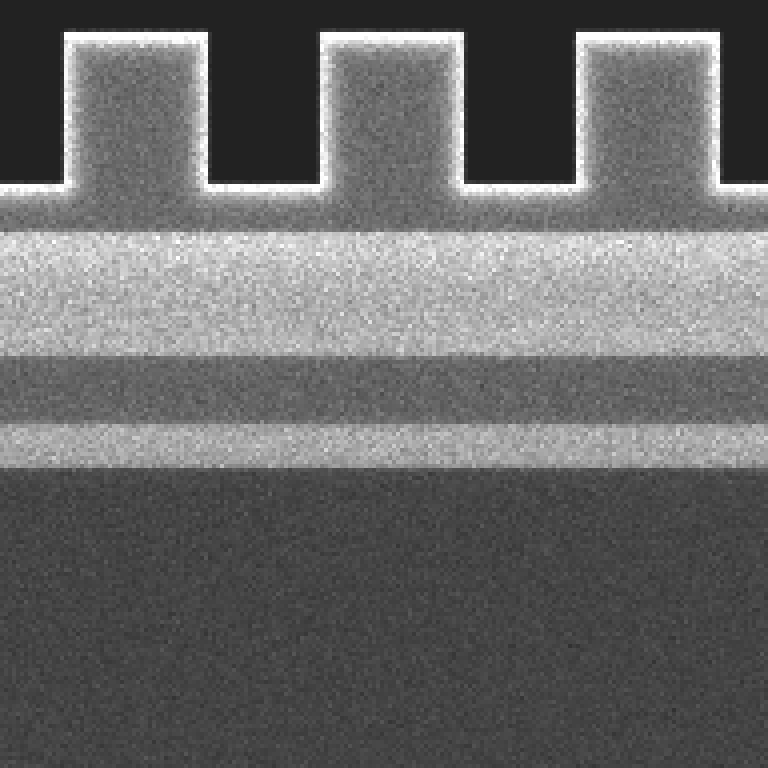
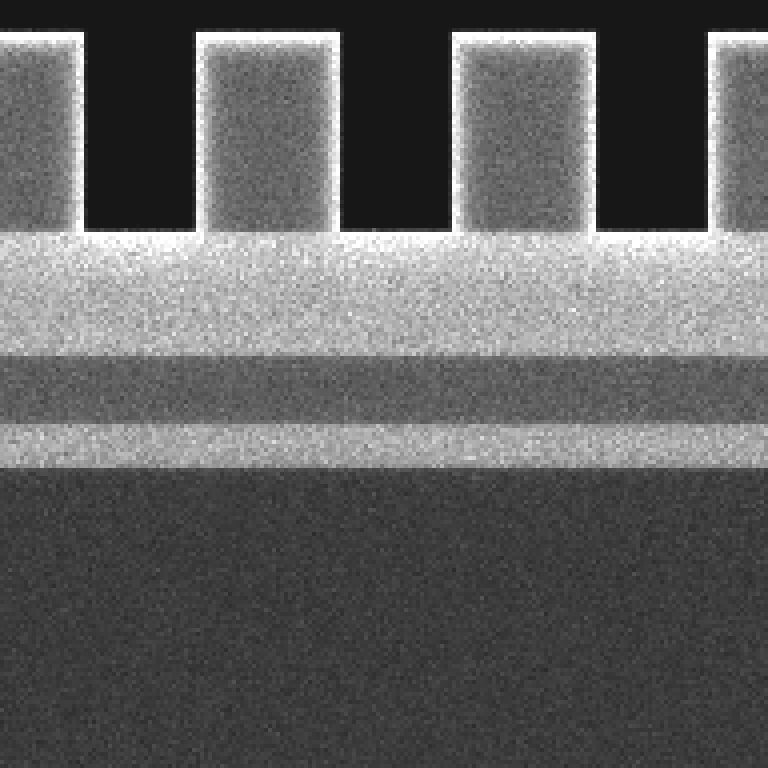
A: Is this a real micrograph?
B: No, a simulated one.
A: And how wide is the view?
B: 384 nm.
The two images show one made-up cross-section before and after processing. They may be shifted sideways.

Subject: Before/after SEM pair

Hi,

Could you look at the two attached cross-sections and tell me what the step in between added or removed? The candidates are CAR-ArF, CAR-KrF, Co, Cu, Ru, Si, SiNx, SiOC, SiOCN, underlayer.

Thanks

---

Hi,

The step removed underlayer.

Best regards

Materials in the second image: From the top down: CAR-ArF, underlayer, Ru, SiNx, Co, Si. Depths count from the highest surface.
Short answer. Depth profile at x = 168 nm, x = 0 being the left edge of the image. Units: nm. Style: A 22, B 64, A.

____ CAR-ArF 76, underlayer 24, Ru 62, SiNx 34, Co 22, Si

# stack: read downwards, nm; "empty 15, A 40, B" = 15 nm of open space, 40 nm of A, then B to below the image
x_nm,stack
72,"empty 100, Ru 62, SiNx 34, Co 22, Si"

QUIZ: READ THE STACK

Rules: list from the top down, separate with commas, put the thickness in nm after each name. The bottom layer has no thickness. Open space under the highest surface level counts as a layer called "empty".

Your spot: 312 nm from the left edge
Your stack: empty 100, Ru 62, SiNx 34, Co 22, Si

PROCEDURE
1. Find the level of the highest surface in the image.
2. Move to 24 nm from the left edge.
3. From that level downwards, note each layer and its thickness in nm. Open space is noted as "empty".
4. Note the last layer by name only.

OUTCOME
CAR-ArF 76, underlayer 24, Ru 62, SiNx 34, Co 22, Si